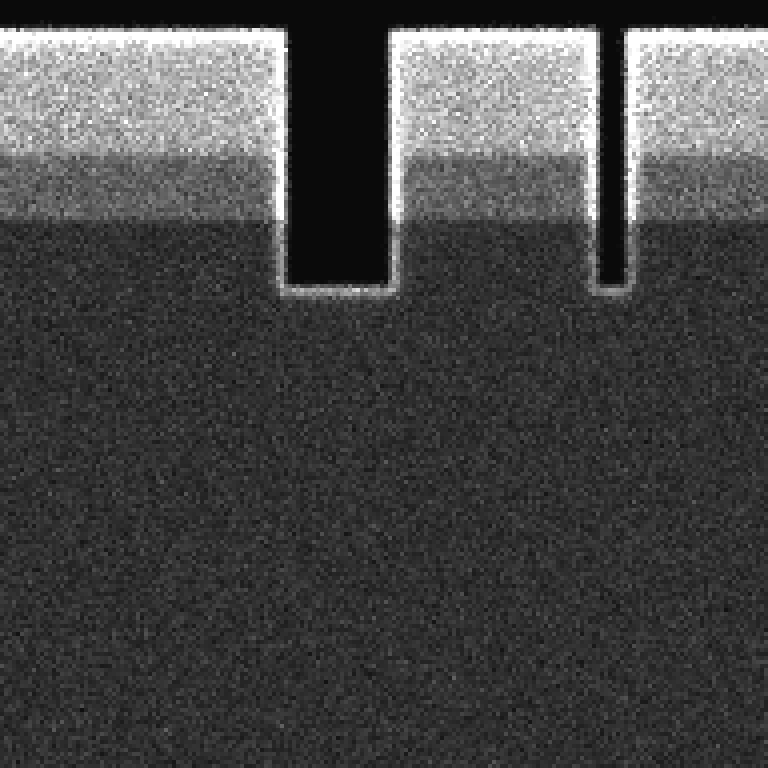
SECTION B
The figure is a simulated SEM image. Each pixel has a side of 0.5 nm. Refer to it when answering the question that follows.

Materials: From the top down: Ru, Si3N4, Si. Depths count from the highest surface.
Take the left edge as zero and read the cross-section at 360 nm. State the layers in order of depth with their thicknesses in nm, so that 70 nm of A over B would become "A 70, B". Ru 62, Si3N4 32, Si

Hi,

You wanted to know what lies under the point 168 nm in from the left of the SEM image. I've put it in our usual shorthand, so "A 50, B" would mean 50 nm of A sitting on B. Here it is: empty 128, Si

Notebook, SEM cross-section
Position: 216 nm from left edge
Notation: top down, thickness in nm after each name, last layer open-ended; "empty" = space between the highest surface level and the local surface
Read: Ru 62, Si3N4 32, Si